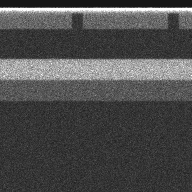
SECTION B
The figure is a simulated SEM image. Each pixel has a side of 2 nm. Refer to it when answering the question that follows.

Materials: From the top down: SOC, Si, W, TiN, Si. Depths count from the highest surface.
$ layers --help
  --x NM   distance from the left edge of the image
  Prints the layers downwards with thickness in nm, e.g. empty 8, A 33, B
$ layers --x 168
SOC 42, Si 60, W 42, TiN 42, Si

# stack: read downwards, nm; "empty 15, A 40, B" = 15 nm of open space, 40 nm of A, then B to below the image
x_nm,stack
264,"SOC 42, Si 60, W 42, TiN 42, Si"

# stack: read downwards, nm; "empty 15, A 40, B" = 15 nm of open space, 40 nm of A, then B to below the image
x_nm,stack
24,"SOC 42, Si 60, W 42, TiN 42, Si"